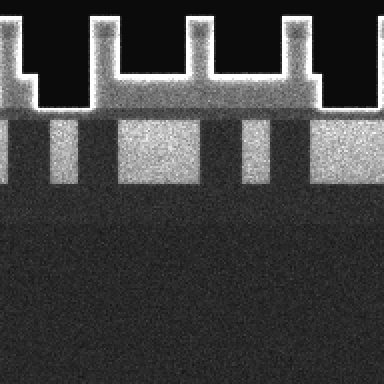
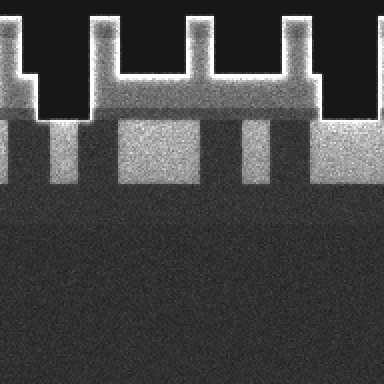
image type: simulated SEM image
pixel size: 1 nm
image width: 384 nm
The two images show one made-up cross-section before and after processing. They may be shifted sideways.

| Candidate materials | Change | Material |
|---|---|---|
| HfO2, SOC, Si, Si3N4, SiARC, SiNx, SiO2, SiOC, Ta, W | removed | SiNx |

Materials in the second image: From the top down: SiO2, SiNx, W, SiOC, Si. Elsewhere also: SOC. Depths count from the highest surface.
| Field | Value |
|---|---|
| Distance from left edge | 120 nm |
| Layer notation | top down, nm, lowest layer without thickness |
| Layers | empty 58, SiO2 34, SiNx 12, W 64, SiOC 40, Si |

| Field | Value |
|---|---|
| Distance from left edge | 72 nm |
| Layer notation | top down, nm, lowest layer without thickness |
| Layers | empty 104, W 64, SiOC 40, Si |